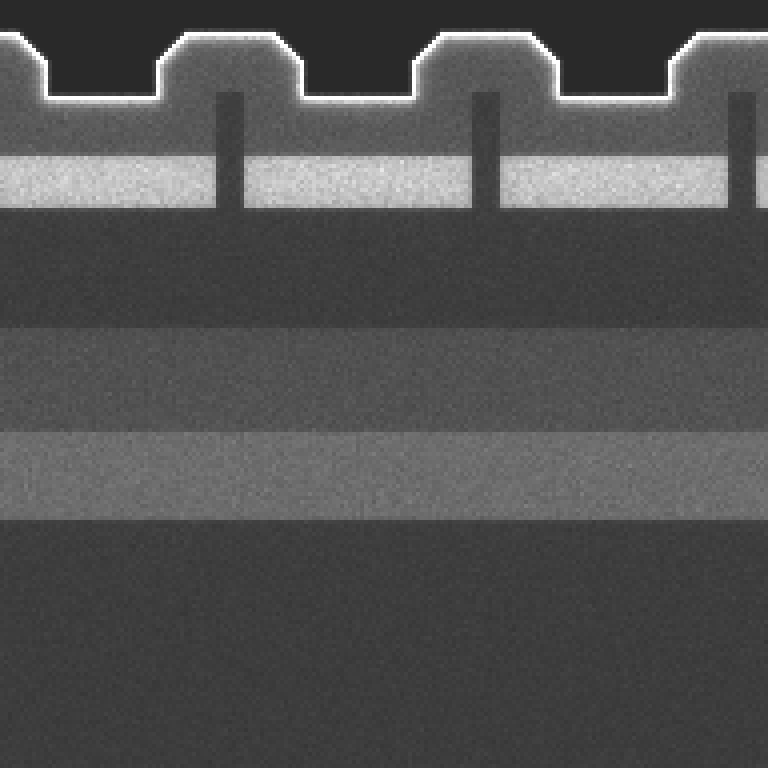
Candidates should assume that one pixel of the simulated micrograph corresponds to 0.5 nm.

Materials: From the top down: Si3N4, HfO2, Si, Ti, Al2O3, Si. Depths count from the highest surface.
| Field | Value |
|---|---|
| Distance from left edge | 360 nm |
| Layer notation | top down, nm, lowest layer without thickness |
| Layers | Si3N4 62, HfO2 26, Si 60, Ti 52, Al2O3 44, Si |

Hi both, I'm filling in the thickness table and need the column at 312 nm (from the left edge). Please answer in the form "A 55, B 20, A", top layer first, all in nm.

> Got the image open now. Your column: empty 32, Si3N4 30, HfO2 26, Si 60, Ti 52, Al2O3 44, Si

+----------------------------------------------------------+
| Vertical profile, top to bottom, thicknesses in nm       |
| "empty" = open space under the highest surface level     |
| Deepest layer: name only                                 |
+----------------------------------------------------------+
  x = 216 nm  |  empty 4, Si3N4 58, HfO2 26, Si 60, Ti 52, Al2O3 44, Si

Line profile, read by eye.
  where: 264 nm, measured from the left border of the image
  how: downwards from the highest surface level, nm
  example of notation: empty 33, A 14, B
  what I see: Si3N4 62, HfO2 26, Si 60, Ti 52, Al2O3 44, Si